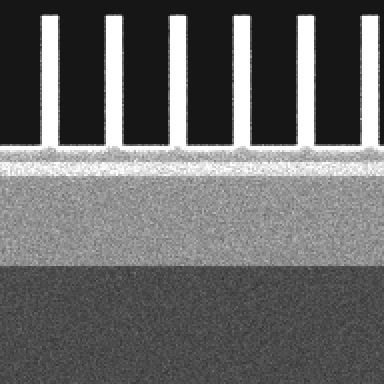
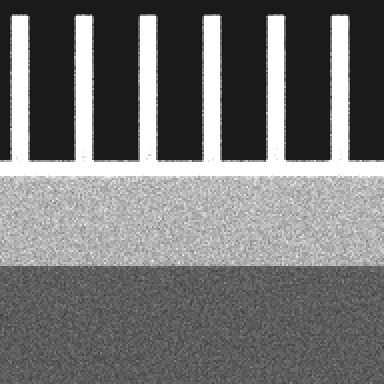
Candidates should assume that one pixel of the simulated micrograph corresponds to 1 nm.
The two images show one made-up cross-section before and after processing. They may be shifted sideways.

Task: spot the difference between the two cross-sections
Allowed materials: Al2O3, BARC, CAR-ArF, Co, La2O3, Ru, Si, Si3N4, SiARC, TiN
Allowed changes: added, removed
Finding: removed TiN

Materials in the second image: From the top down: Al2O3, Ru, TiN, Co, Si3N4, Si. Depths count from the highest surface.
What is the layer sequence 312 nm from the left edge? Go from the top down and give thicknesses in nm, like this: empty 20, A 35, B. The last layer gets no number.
empty 146, Co 14, Si3N4 90, Si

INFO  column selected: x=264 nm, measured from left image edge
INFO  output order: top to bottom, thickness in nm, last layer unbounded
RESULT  empty 146, Co 14, Si3N4 90, Si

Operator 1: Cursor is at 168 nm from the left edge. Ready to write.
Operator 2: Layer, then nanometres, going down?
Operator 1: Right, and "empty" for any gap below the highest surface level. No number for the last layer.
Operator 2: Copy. empty 146, Co 14, Si3N4 90, Si